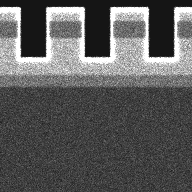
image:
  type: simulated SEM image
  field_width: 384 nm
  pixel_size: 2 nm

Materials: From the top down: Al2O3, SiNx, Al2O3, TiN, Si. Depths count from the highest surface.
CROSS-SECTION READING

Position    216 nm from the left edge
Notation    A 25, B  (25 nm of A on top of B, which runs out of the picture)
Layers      empty 100, Al2O3 34, TiN 24, Si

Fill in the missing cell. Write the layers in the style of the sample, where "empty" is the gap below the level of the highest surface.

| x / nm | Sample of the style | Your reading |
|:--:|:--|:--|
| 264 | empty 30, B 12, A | Al2O3 26, SiNx 34, Al2O3 74, TiN 24, Si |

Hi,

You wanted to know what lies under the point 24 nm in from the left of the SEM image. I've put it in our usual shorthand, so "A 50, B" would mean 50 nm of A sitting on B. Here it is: Al2O3 26, SiNx 34, Al2O3 74, TiN 24, Si